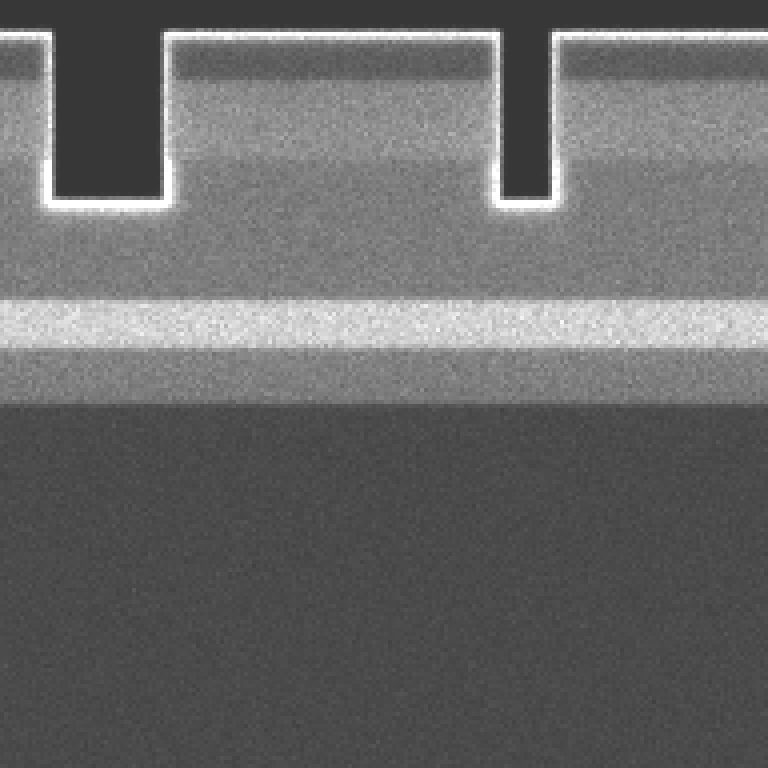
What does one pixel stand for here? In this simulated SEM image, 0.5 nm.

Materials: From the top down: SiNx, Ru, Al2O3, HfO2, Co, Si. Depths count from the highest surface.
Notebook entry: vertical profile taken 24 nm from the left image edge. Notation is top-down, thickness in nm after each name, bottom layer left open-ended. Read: SiNx 24, Ru 40, Al2O3 70, HfO2 24, Co 28, Si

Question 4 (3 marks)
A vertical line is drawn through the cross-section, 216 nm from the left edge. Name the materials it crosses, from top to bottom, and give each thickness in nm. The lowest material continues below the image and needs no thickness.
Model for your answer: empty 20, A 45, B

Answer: SiNx 24, Ru 40, Al2O3 70, HfO2 24, Co 28, Si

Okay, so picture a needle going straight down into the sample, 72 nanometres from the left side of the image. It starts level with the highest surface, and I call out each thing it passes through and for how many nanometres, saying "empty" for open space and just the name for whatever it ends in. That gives empty 84, Al2O3 50, HfO2 24, Co 28, Si